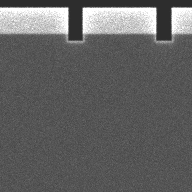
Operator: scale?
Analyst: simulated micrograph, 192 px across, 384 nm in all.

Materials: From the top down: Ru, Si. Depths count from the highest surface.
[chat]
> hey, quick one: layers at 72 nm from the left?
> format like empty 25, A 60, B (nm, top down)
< Ru 52, Si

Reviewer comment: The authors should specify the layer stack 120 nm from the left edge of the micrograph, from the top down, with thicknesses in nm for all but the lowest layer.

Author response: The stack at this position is Ru 52, Si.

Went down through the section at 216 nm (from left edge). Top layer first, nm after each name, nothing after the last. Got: Ru 52, Si